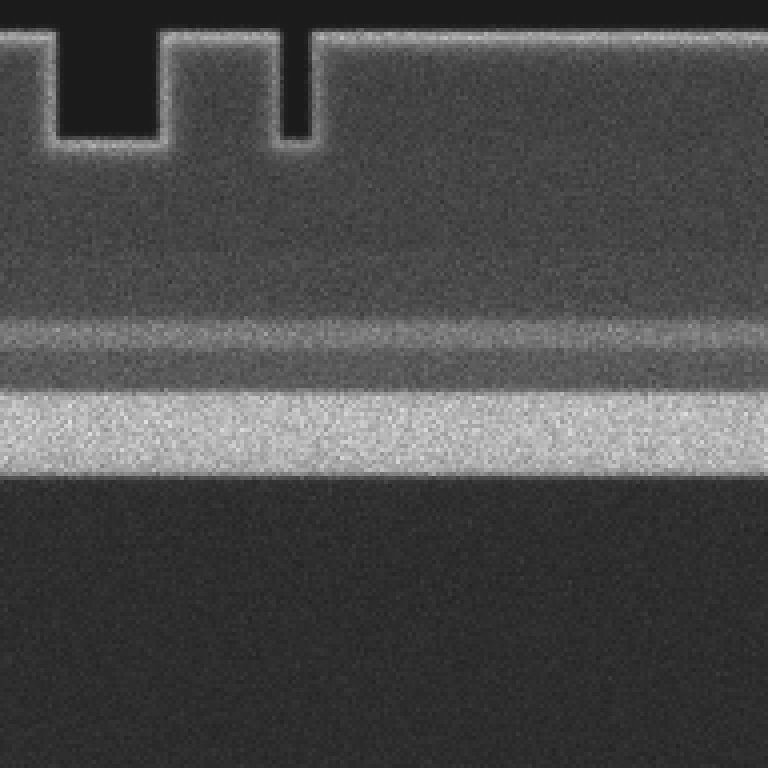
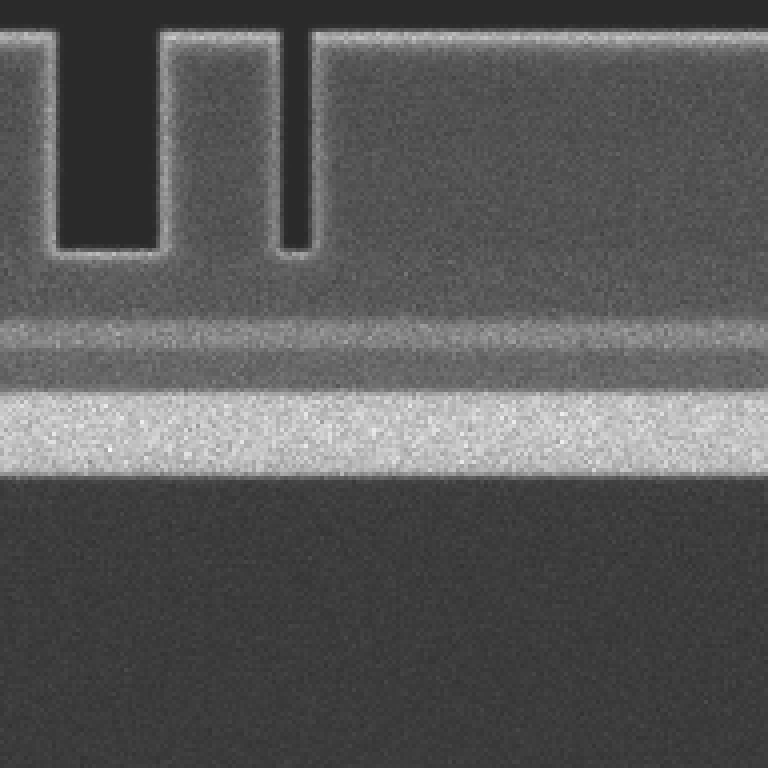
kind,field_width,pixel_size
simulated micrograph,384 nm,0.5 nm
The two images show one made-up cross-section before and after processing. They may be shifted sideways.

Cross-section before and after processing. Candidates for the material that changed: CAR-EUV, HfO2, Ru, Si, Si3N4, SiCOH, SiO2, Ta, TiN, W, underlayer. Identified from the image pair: underlayer (removed).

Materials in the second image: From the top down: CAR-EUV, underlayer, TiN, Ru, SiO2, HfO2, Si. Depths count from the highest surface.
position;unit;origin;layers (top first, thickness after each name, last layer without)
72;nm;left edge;empty 110, TiN 34, Ru 14, SiO2 22, HfO2 42, Si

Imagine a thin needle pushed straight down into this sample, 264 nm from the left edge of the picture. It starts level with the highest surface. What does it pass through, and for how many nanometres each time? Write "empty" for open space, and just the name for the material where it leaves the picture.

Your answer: CAR-EUV 54, underlayer 56, TiN 34, Ru 14, SiO2 22, HfO2 42, Si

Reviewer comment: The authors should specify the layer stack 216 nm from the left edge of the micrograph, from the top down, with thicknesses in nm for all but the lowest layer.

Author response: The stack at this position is CAR-EUV 54, underlayer 56, TiN 34, Ru 14, SiO2 22, HfO2 42, Si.